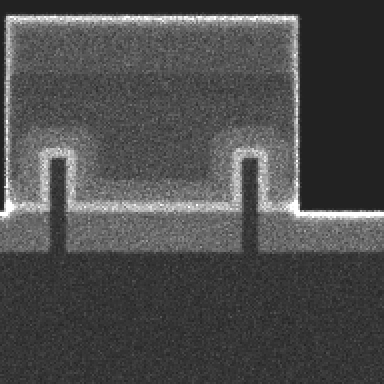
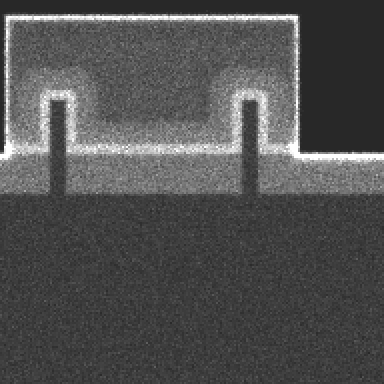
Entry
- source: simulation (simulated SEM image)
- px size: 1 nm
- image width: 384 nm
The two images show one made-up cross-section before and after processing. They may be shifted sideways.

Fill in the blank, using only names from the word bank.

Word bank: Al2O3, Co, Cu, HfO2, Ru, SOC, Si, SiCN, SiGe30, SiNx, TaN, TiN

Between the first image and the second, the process removed SOC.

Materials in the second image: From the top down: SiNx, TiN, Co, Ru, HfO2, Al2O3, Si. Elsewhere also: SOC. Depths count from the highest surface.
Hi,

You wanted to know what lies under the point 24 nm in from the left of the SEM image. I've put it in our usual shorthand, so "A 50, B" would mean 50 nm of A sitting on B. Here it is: SiNx 24, TiN 36, Co 56, Ru 12, HfO2 10, Al2O3 40, Si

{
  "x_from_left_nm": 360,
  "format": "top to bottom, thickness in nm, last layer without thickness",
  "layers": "empty 138, Al2O3 40, Si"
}